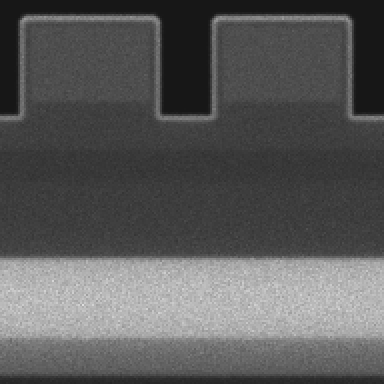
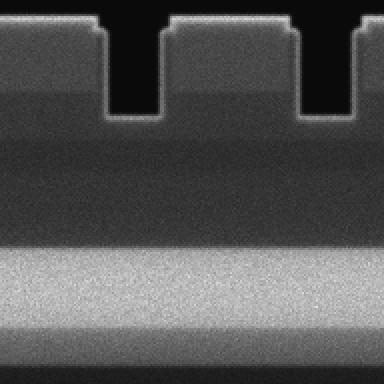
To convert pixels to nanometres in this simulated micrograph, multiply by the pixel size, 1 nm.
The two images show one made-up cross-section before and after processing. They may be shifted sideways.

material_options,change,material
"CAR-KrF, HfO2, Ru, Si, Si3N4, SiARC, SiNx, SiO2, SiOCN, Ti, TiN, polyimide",removed,SiOCN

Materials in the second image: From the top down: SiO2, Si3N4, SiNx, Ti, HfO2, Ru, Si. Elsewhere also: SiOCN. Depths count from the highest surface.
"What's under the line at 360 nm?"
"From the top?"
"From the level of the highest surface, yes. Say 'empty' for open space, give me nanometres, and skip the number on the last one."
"empty 12, SiOCN 88, Si3N4 24, SiNx 32, Ti 76, HfO2 80, Ru 38, Si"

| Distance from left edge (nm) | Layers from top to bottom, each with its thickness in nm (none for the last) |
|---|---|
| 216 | SiO2 76, Si3N4 48, SiNx 32, Ti 76, HfO2 80, Ru 38, Si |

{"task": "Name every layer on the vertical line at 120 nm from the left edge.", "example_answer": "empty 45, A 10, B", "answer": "empty 100, Si3N4 24, SiNx 32, Ti 76, HfO2 80, Ru 38, Si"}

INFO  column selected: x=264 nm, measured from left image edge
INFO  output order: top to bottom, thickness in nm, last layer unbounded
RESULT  SiO2 76, Si3N4 48, SiNx 32, Ti 76, HfO2 80, Ru 38, Si